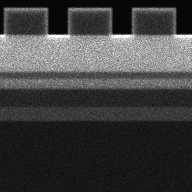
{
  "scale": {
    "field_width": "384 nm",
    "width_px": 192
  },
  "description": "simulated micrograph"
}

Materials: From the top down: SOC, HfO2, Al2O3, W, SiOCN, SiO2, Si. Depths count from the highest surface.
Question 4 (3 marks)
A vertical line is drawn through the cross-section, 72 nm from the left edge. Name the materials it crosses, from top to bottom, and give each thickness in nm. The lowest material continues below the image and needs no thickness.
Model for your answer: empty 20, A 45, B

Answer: SOC 54, HfO2 74, Al2O3 14, W 20, SiOCN 36, SiO2 28, Si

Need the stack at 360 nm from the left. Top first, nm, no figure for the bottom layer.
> empty 54, HfO2 74, Al2O3 14, W 20, SiOCN 36, SiO2 28, Si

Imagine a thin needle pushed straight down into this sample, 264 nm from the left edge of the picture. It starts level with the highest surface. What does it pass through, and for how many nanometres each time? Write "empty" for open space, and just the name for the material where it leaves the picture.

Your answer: SOC 54, HfO2 74, Al2O3 14, W 20, SiOCN 36, SiO2 28, Si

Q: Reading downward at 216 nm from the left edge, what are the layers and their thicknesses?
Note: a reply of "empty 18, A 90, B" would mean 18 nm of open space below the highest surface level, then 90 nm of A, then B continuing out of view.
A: SOC 54, HfO2 74, Al2O3 14, W 20, SiOCN 36, SiO2 28, Si